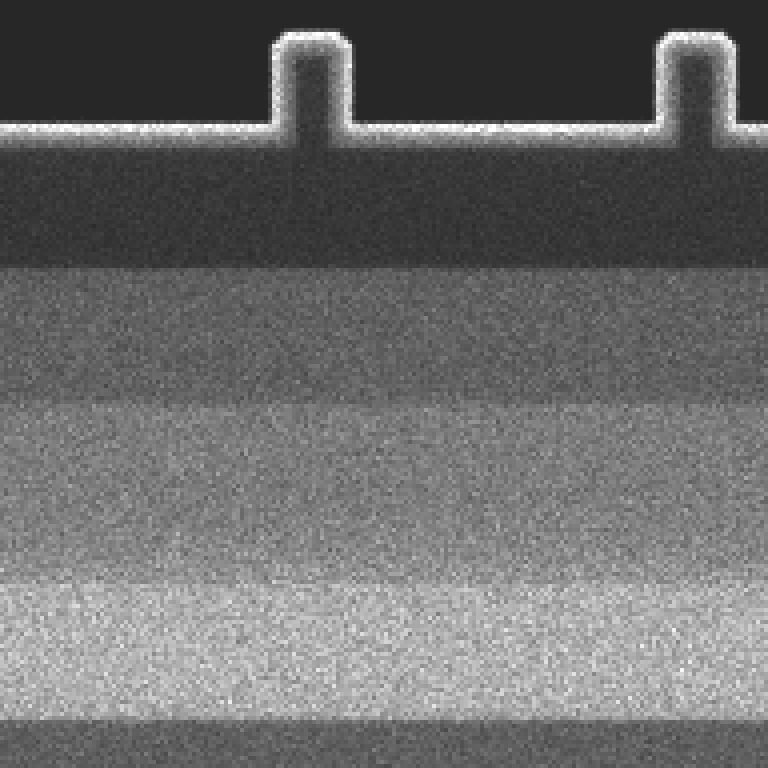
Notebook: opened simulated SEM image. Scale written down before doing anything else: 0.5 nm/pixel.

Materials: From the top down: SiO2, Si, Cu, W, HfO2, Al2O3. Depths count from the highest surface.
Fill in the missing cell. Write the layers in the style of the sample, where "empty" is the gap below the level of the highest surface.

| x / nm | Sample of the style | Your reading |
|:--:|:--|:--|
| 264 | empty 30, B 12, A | empty 46, SiO2 12, Si 60, Cu 68, W 90, HfO2 68, Al2O3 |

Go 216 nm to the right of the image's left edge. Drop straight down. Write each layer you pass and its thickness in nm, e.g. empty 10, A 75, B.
empty 46, SiO2 12, Si 60, Cu 68, W 90, HfO2 68, Al2O3